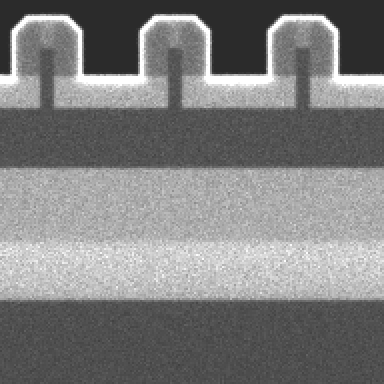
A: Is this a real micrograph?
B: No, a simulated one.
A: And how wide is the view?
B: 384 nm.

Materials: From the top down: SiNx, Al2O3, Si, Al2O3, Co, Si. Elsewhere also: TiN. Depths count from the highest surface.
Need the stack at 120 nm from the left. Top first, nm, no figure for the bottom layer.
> empty 60, Al2O3 32, Si 60, Al2O3 74, Co 58, Si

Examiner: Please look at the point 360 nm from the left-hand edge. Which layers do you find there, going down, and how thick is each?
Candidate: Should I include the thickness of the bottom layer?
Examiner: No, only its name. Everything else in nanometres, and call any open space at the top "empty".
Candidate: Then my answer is empty 60, Al2O3 32, Si 60, Al2O3 74, Co 58, Si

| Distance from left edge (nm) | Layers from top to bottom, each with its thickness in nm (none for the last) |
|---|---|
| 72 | empty 6, SiNx 54, Al2O3 32, Si 60, Al2O3 74, Co 58, Si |